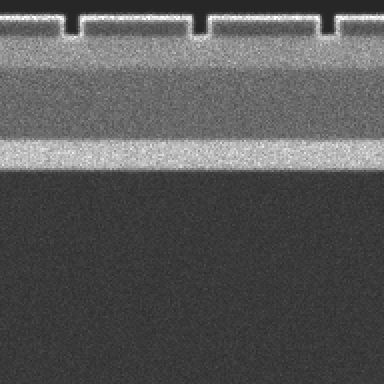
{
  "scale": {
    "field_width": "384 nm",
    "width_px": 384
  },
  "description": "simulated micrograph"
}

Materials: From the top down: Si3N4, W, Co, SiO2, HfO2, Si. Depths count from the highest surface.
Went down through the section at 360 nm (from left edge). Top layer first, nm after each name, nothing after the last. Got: Si3N4 20, W 32, Co 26, SiO2 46, HfO2 30, Si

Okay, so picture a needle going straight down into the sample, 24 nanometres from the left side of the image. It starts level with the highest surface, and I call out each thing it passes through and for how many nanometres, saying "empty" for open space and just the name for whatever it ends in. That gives Si3N4 20, W 32, Co 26, SiO2 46, HfO2 30, Si